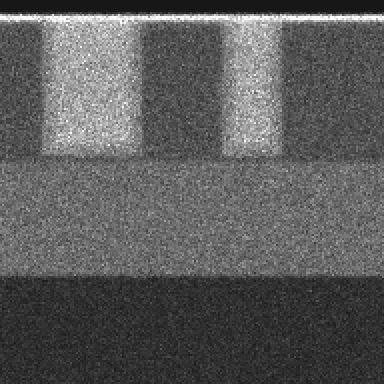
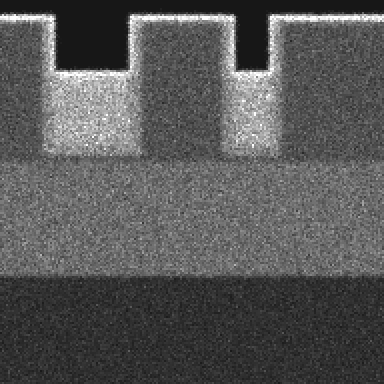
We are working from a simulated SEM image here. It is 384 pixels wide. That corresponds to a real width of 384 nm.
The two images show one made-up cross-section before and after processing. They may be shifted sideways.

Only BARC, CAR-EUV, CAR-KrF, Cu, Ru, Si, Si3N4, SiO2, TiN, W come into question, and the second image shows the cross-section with W removed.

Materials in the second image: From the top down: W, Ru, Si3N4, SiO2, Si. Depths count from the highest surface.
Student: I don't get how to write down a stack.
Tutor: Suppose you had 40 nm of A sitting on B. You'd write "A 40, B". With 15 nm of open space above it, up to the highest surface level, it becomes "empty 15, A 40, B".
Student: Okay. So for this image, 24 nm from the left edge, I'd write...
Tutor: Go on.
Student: Si3N4 146, SiO2 114, Si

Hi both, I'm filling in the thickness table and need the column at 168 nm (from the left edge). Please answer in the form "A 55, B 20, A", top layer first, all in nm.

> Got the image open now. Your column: Si3N4 146, SiO2 114, Si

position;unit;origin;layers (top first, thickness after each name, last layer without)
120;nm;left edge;empty 56, W 72, Ru 12, Si3N4 6, SiO2 114, Si